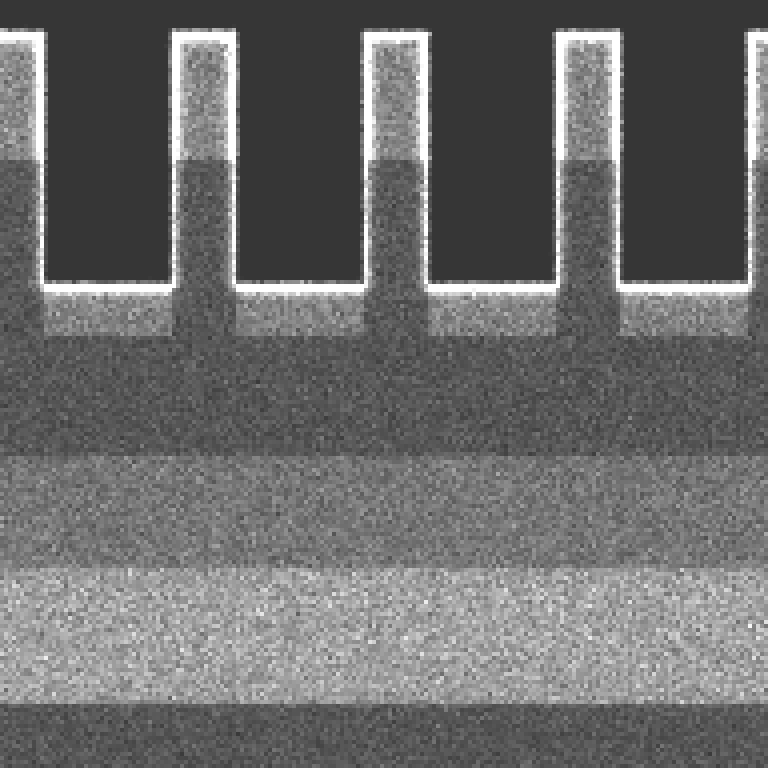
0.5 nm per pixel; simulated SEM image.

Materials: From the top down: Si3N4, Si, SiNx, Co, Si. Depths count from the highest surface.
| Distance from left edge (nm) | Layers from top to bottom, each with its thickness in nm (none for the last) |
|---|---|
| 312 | empty 126, Si3N4 26, Si 60, SiNx 56, Co 68, Si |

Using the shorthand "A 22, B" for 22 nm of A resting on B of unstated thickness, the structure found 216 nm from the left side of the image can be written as empty 126, Si3N4 26, Si 60, SiNx 56, Co 68, Si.